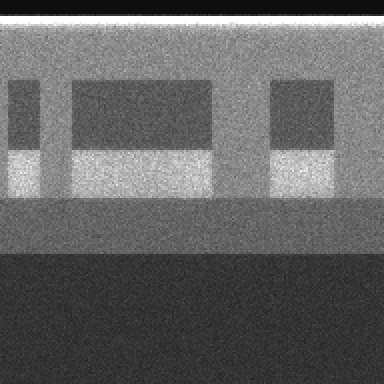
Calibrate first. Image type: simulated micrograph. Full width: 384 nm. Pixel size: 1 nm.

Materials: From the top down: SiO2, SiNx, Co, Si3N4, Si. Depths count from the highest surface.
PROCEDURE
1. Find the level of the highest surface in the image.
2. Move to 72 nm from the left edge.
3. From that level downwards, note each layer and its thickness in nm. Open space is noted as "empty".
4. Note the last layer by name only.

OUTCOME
SiO2 64, SiNx 70, Co 48, Si3N4 56, Si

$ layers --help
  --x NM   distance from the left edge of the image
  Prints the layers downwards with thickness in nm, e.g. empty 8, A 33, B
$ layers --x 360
SiO2 182, Si3N4 56, Si